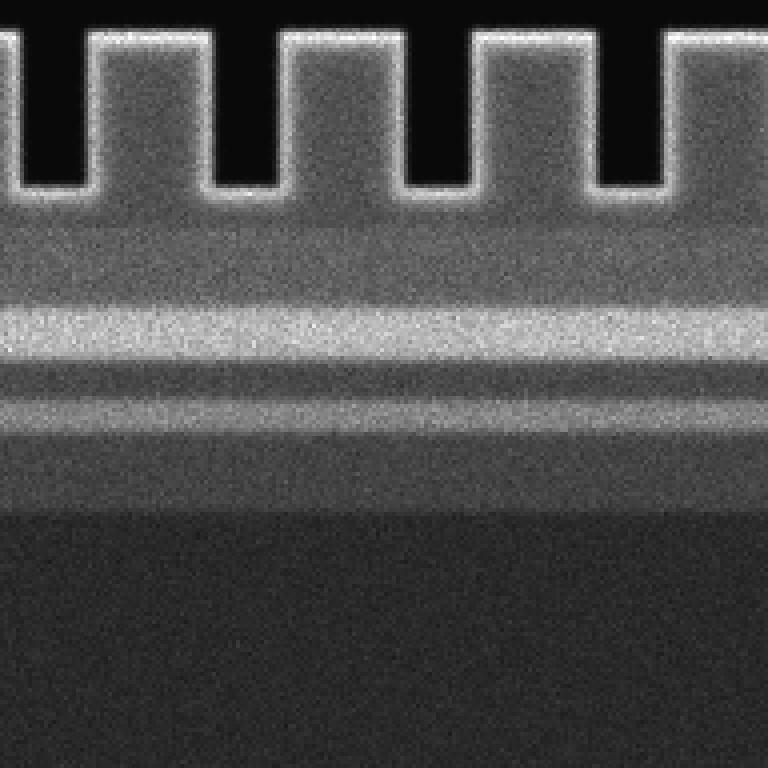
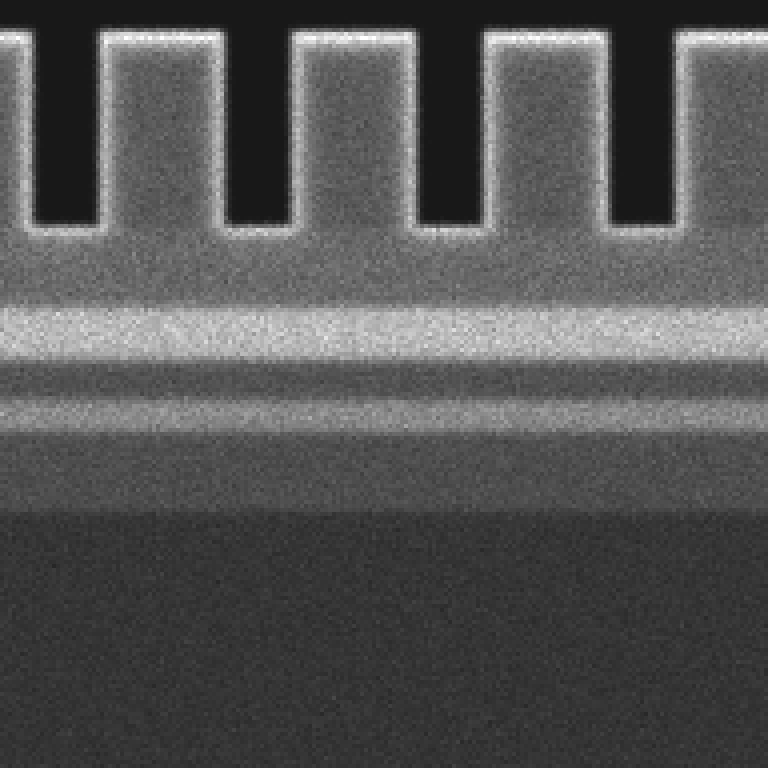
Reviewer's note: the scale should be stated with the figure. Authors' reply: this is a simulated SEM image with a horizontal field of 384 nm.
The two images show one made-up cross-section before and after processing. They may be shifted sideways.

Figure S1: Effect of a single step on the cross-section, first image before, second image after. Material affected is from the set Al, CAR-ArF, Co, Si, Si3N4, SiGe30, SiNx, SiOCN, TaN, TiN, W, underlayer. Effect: removed underlayer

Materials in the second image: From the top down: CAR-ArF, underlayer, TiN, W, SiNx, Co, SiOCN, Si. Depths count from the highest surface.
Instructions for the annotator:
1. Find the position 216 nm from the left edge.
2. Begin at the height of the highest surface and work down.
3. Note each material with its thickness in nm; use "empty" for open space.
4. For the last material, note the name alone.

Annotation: empty 98, TiN 40, W 26, SiNx 20, Co 16, SiOCN 40, Si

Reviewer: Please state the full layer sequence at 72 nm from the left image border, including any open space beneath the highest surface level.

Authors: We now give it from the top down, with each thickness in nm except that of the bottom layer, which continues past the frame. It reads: CAR-ArF 78, underlayer 20, TiN 40, W 26, SiNx 20, Co 16, SiOCN 40, Si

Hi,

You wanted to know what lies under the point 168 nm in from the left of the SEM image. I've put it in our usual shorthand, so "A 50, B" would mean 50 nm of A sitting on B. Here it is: CAR-ArF 78, underlayer 20, TiN 40, W 26, SiNx 20, Co 16, SiOCN 40, Si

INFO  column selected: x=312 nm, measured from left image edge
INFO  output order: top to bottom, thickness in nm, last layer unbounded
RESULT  empty 98, TiN 40, W 26, SiNx 20, Co 16, SiOCN 40, Si